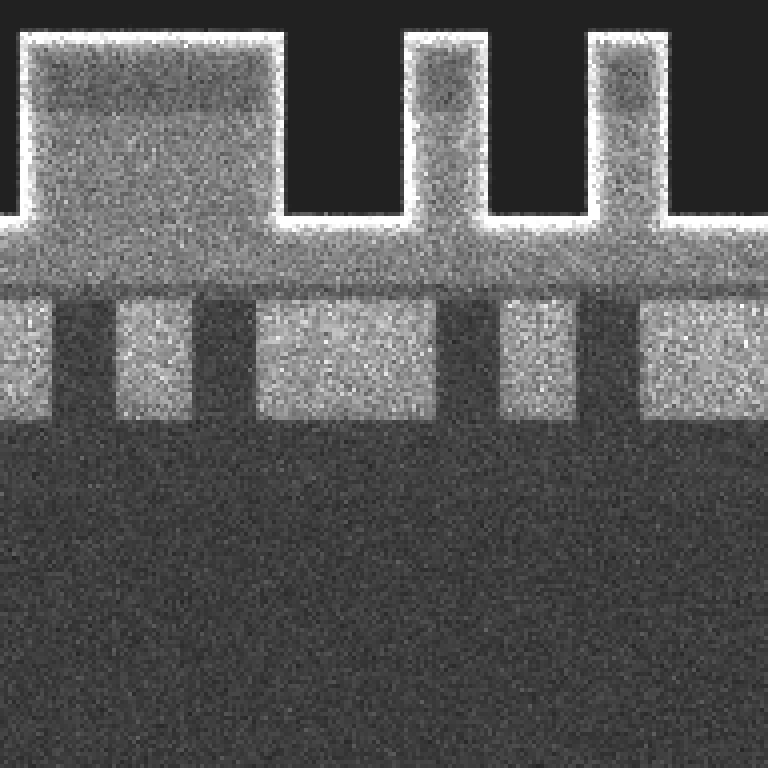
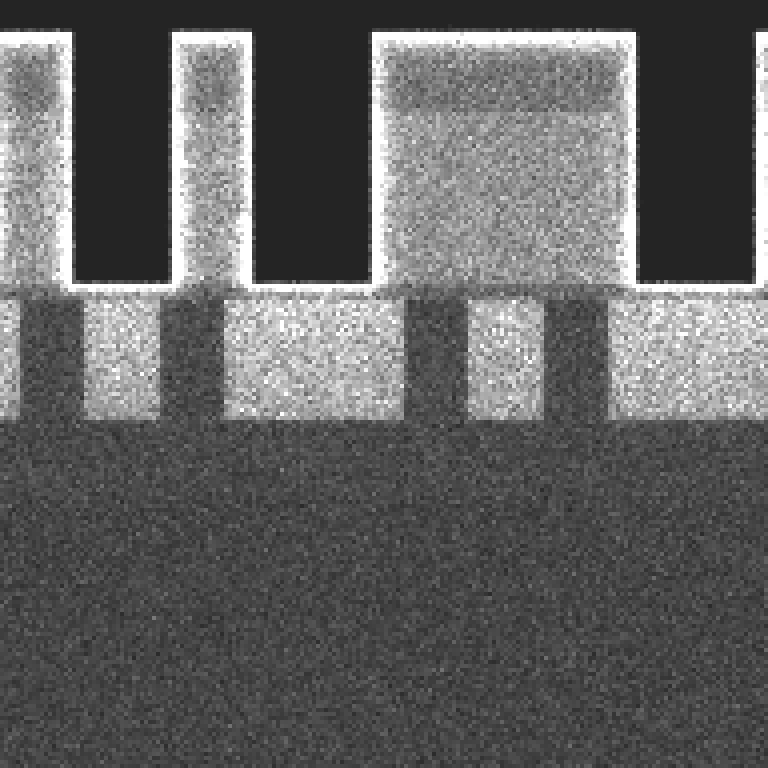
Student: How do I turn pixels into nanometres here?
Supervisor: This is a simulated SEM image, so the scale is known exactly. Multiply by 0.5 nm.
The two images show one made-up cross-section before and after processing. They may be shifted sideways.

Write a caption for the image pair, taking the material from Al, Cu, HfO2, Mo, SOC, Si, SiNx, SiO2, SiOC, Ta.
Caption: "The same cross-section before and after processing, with SiO2 removed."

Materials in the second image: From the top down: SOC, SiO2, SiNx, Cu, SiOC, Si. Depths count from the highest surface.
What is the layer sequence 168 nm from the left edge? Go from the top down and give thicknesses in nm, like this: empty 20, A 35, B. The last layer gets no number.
empty 126, SiNx 8, Cu 60, SiOC 38, Si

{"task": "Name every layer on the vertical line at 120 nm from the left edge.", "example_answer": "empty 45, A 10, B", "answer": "SOC 92, SiO2 34, SiNx 8, Cu 60, SiOC 38, Si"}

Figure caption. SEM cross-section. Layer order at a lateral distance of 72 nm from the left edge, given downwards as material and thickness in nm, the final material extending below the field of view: empty 126, SiNx 8, Cu 60, SiOC 38, Si